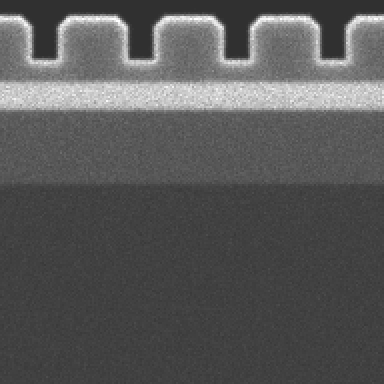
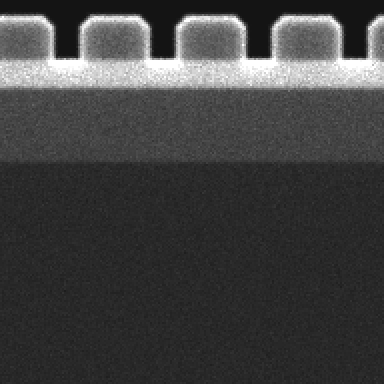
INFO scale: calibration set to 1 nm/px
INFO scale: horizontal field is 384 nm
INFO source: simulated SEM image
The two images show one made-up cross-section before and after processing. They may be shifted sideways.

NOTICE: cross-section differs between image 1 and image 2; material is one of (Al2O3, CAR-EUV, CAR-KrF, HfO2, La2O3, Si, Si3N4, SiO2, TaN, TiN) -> removed: Al2O3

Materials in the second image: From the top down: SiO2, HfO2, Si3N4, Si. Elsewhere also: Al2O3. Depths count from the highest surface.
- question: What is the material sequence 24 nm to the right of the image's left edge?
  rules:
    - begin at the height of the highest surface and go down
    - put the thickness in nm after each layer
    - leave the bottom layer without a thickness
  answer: SiO2 44, HfO2 28, Si3N4 74, Si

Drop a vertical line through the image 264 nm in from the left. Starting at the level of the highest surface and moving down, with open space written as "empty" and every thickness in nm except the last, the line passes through empty 44, HfO2 28, Si3N4 74, Si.